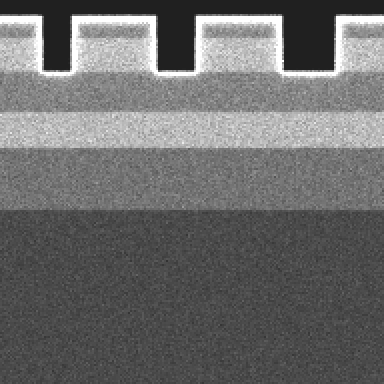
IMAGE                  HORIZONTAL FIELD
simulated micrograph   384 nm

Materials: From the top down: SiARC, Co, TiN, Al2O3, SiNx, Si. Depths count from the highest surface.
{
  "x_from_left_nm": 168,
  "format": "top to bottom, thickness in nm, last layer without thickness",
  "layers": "empty 56, TiN 40, Al2O3 36, SiNx 62, Si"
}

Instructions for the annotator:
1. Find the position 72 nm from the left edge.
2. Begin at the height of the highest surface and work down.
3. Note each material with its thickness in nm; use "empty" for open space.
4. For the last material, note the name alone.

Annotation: SiARC 22, Co 34, TiN 40, Al2O3 36, SiNx 62, Si